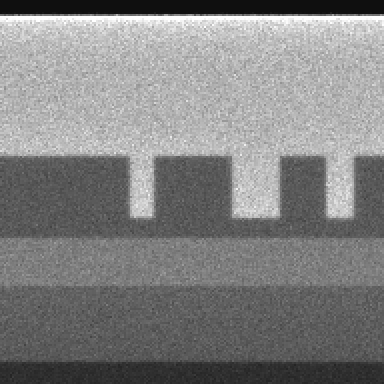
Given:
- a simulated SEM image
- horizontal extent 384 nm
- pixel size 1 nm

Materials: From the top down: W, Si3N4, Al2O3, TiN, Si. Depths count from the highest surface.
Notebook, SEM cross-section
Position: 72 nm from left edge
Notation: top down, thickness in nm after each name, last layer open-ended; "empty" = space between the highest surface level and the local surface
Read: W 140, Si3N4 82, Al2O3 48, TiN 76, Si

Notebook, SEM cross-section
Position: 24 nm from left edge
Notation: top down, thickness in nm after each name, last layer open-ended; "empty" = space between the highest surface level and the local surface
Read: W 140, Si3N4 82, Al2O3 48, TiN 76, Si